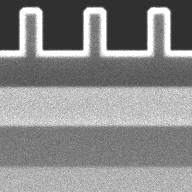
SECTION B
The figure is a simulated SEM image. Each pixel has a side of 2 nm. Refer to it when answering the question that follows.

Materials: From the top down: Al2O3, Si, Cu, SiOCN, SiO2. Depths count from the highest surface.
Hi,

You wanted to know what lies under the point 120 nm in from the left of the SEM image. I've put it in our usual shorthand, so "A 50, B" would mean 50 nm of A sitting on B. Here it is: empty 86, Al2O3 12, Si 60, Cu 78, SiOCN 82, SiO2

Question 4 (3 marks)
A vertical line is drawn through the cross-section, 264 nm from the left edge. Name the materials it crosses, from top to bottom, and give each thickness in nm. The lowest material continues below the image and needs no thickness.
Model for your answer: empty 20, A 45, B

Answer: empty 86, Al2O3 12, Si 60, Cu 78, SiOCN 82, SiO2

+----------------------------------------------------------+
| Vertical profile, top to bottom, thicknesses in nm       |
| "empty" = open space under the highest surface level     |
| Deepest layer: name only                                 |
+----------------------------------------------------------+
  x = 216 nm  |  empty 86, Al2O3 12, Si 60, Cu 78, SiOCN 82, SiO2